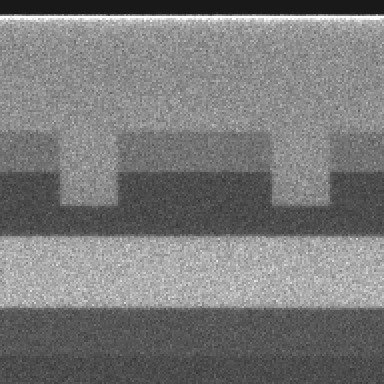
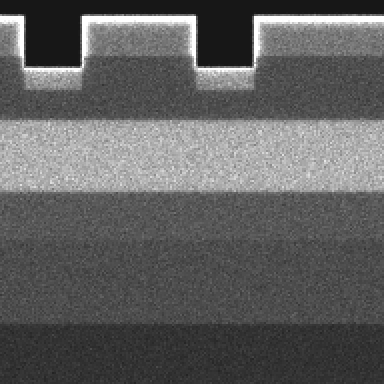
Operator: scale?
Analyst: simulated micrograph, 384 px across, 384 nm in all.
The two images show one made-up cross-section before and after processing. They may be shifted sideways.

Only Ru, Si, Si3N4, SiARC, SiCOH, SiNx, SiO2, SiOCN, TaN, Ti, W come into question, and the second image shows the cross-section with Ru removed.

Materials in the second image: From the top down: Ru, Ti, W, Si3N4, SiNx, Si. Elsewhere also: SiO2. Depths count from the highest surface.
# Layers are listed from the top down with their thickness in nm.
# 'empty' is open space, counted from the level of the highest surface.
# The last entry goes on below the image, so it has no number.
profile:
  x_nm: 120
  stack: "SiO2 40, Ti 64, W 72, Si3N4 48, SiNx 84, Si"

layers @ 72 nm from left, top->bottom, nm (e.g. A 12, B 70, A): empty 52, Ru 22, Ti 30, W 72, Si3N4 48, SiNx 84, Si